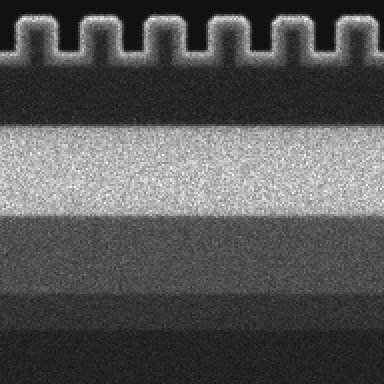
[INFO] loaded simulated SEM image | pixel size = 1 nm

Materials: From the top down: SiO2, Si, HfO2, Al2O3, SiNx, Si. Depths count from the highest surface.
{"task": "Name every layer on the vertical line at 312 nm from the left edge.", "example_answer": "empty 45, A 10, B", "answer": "empty 6, SiO2 44, Si 60, HfO2 90, Al2O3 78, SiNx 36, Si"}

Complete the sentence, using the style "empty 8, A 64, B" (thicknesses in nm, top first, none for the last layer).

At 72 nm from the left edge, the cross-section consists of empty 36, SiO2 14, Si 60, HfO2 90, Al2O3 78, SiNx 36, Si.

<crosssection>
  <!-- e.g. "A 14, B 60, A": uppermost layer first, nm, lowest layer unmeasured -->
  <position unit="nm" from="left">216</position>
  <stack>SiO2 50, Si 60, HfO2 90, Al2O3 78, SiNx 36, Si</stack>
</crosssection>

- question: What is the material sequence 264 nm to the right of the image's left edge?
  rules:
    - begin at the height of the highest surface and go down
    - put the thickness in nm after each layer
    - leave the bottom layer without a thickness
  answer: empty 36, SiO2 14, Si 60, HfO2 90, Al2O3 78, SiNx 36, Si